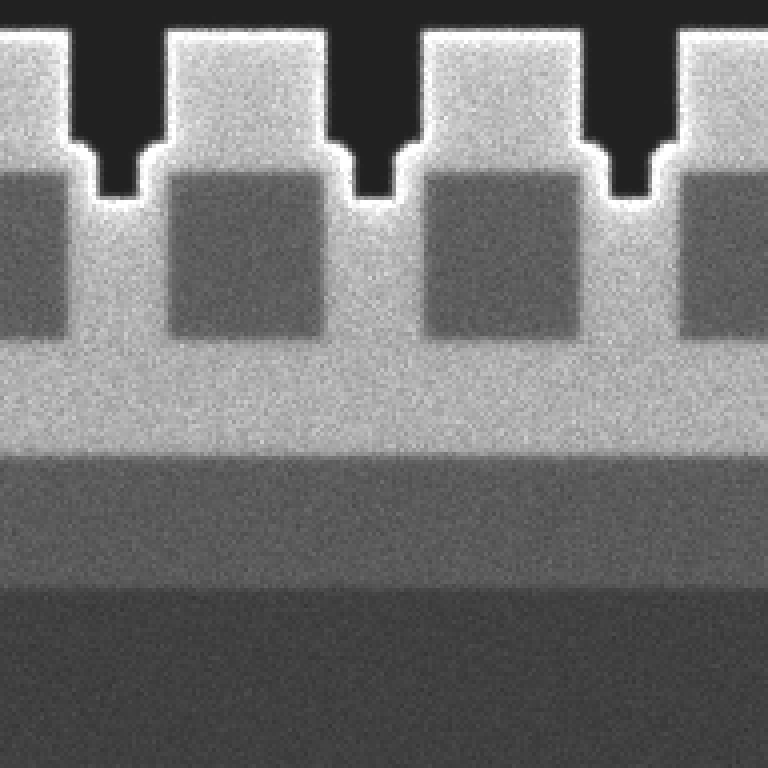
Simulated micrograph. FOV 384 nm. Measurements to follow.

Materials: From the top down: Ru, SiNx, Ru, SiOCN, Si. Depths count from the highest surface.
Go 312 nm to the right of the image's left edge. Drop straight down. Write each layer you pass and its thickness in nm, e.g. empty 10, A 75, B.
empty 84, Ru 128, SiOCN 66, Si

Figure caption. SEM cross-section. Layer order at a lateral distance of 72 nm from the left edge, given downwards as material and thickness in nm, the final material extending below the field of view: empty 60, Ru 152, SiOCN 66, Si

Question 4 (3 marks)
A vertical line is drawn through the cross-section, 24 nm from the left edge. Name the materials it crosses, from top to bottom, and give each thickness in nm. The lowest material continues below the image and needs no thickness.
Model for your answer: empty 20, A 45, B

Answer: Ru 70, SiNx 84, Ru 58, SiOCN 66, Si